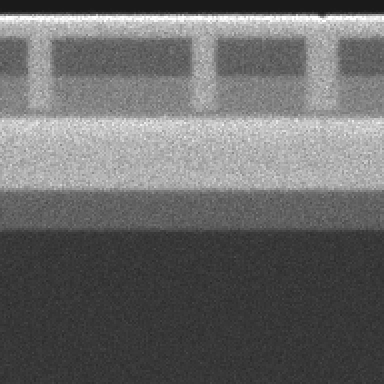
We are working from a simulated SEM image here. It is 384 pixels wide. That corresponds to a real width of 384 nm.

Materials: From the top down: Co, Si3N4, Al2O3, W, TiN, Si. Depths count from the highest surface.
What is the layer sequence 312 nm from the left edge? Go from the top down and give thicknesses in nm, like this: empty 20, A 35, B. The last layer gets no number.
Co 94, Al2O3 8, W 72, TiN 40, Si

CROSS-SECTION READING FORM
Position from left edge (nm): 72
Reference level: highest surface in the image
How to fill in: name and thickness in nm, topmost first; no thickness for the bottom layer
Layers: Co 22, Si3N4 38, Al2O3 42, W 72, TiN 40, Si